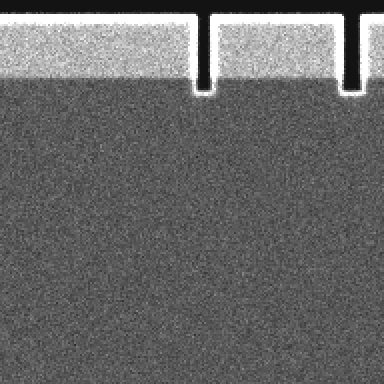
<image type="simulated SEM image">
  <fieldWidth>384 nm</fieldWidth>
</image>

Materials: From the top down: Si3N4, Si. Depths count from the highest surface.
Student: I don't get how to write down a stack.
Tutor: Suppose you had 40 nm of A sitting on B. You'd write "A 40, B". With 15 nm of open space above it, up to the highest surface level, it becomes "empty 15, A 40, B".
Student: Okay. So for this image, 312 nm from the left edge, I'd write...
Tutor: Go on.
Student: Si3N4 62, Si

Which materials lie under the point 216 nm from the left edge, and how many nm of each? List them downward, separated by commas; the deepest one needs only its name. Si3N4 62, Si